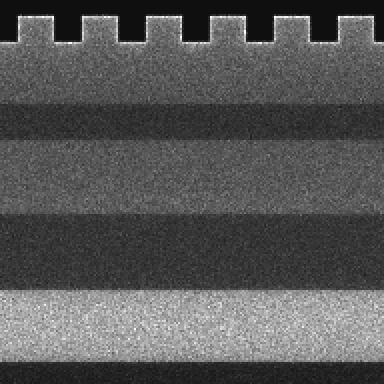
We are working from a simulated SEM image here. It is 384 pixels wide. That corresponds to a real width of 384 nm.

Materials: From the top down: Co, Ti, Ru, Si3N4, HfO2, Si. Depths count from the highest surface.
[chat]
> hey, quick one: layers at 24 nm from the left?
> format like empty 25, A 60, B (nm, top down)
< Co 88, Ti 36, Ru 74, Si3N4 76, HfO2 72, Si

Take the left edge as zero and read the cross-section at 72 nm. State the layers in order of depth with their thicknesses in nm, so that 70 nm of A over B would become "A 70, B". empty 26, Co 62, Ti 36, Ru 74, Si3N4 76, HfO2 72, Si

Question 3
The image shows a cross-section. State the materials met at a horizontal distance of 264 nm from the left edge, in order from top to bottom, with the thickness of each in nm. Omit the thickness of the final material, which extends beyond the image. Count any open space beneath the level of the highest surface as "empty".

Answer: empty 26, Co 62, Ti 36, Ru 74, Si3N4 76, HfO2 72, Si